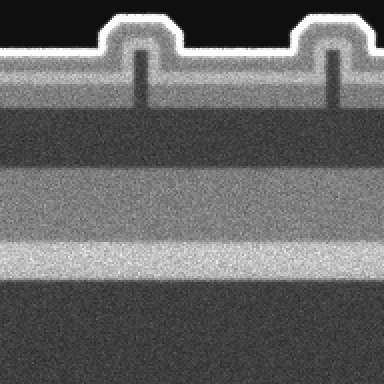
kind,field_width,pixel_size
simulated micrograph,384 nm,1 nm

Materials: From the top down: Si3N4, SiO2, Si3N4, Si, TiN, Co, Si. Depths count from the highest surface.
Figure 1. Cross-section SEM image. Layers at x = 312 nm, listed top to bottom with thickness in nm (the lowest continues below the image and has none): Si3N4 56, SiO2 12, Si3N4 24, Si 60, TiN 74, Co 38, Si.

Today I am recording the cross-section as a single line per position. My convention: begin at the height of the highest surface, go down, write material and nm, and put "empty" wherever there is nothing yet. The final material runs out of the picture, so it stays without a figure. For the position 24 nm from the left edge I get empty 34, Si3N4 22, SiO2 12, Si3N4 24, Si 60, TiN 74, Co 38, Si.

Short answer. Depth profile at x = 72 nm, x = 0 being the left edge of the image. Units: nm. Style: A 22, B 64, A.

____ empty 34, Si3N4 22, SiO2 12, Si3N4 24, Si 60, TiN 74, Co 38, Si